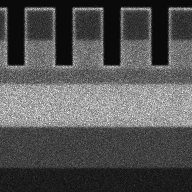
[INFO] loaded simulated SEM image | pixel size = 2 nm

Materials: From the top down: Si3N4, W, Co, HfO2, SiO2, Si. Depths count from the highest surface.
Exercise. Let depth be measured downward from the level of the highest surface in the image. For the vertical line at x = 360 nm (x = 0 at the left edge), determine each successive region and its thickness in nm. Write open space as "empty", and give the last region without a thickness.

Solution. Si3N4 64, W 58, Co 30, HfO2 86, SiO2 82, Si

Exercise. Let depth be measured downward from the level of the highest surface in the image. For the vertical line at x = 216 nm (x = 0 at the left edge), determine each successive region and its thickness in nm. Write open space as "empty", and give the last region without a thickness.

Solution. empty 116, W 6, Co 30, HfO2 86, SiO2 82, Si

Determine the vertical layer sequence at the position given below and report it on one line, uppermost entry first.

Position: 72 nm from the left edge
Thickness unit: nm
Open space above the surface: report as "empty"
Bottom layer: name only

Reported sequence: Si3N4 64, W 58, Co 30, HfO2 86, SiO2 82, Si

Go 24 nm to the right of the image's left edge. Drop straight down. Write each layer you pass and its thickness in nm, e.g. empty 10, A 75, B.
empty 116, W 6, Co 30, HfO2 86, SiO2 82, Si